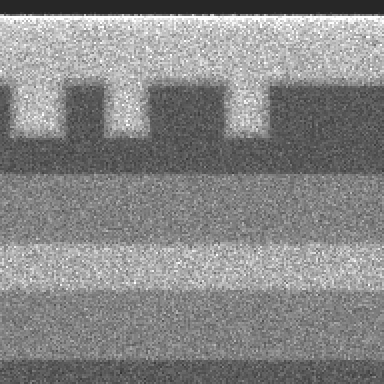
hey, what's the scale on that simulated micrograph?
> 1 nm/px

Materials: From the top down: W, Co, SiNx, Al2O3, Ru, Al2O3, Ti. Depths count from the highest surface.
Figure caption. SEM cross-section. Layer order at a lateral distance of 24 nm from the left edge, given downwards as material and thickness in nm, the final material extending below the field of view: W 114, Co 8, SiNx 36, Al2O3 70, Ru 46, Al2O3 70, Ti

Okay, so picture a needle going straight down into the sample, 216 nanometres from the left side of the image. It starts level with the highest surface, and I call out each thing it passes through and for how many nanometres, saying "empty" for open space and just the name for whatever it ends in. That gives W 62, Co 8, SiNx 88, Al2O3 70, Ru 46, Al2O3 70, Ti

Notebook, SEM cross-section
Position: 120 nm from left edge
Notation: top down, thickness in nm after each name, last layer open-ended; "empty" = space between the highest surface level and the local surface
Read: W 114, Co 8, SiNx 36, Al2O3 70, Ru 46, Al2O3 70, Ti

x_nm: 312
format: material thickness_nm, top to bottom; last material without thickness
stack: W 62, Co 8, SiNx 88, Al2O3 70, Ru 46, Al2O3 70, Ti